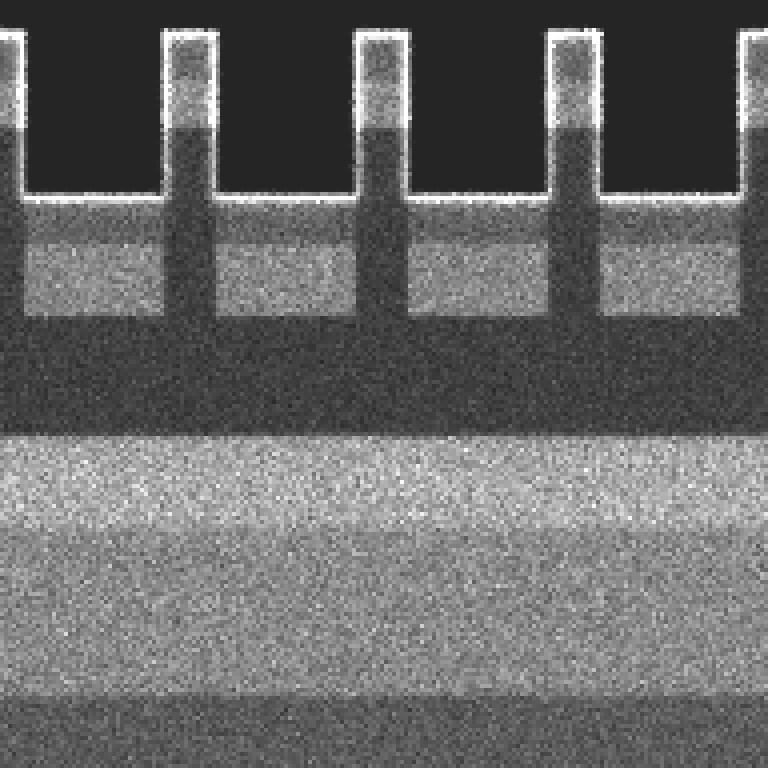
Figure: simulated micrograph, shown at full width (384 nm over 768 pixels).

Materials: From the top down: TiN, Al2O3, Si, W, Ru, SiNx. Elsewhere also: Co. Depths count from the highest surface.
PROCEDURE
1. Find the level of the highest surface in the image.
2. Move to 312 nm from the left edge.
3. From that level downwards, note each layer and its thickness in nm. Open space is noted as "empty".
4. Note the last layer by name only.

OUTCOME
empty 82, TiN 24, Al2O3 36, Si 60, W 46, Ru 84, SiNx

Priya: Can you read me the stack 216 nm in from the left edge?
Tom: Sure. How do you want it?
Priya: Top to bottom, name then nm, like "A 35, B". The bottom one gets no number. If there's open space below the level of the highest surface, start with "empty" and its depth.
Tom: empty 82, TiN 24, Al2O3 36, Si 60, W 46, Ru 84, SiNx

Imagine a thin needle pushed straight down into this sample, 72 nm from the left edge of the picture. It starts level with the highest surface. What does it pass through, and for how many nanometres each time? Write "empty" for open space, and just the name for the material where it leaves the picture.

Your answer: empty 82, TiN 24, Al2O3 36, Si 60, W 46, Ru 84, SiNx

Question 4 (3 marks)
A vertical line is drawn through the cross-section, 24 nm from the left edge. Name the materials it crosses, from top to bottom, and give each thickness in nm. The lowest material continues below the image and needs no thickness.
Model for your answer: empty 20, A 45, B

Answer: empty 82, TiN 24, Al2O3 36, Si 60, W 46, Ru 84, SiNx